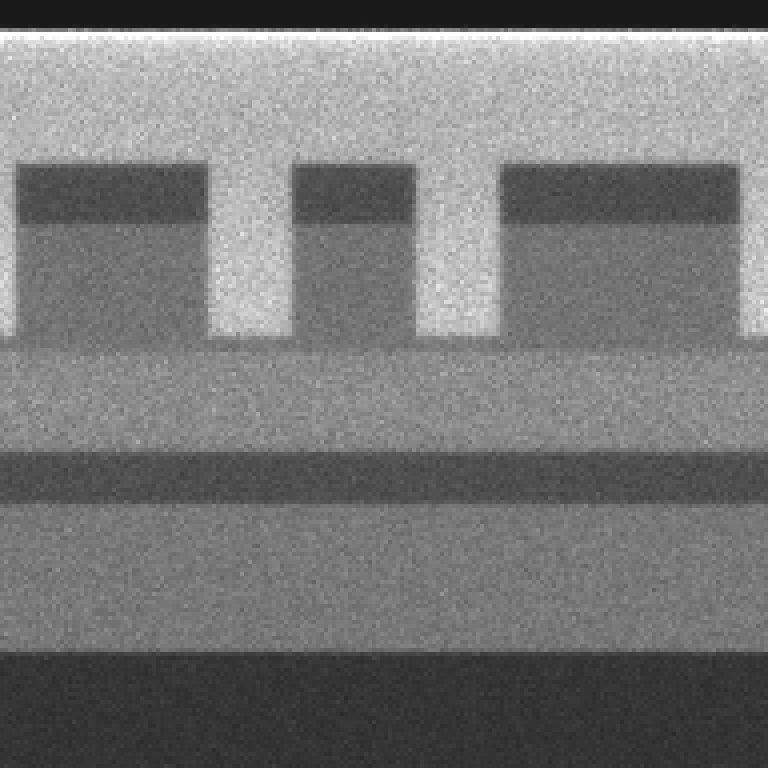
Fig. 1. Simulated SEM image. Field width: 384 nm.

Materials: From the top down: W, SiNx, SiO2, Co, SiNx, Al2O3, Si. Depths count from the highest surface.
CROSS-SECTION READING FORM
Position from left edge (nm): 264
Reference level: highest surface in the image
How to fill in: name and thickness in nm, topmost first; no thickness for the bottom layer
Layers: W 66, SiNx 30, SiO2 64, Co 50, SiNx 26, Al2O3 74, Si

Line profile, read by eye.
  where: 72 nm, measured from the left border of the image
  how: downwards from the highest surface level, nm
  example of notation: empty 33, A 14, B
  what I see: W 66, SiNx 30, SiO2 64, Co 50, SiNx 26, Al2O3 74, Si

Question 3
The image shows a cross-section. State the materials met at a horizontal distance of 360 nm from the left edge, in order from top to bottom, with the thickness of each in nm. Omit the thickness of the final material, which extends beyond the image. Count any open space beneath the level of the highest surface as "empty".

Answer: W 66, SiNx 30, SiO2 64, Co 50, SiNx 26, Al2O3 74, Si